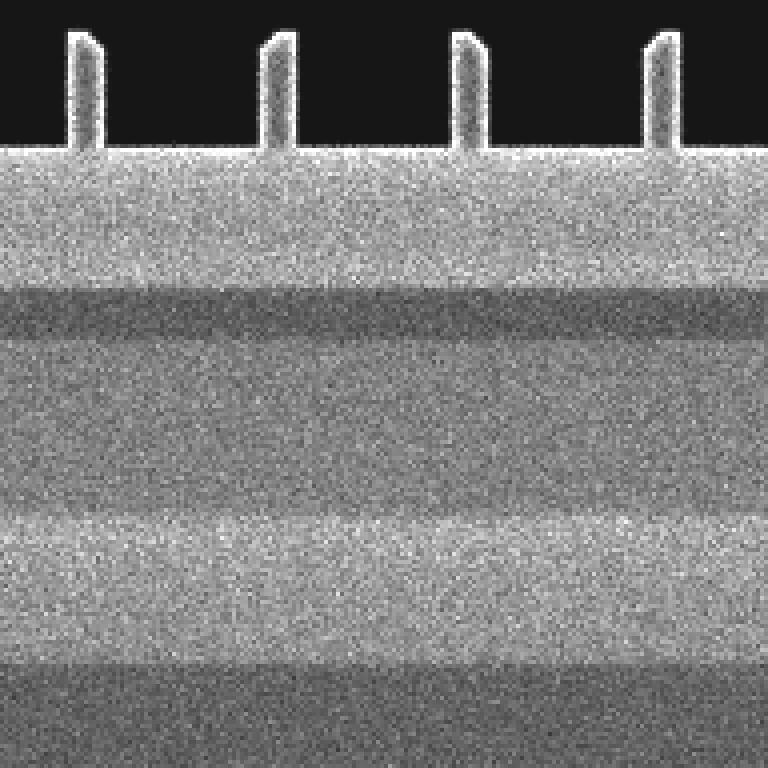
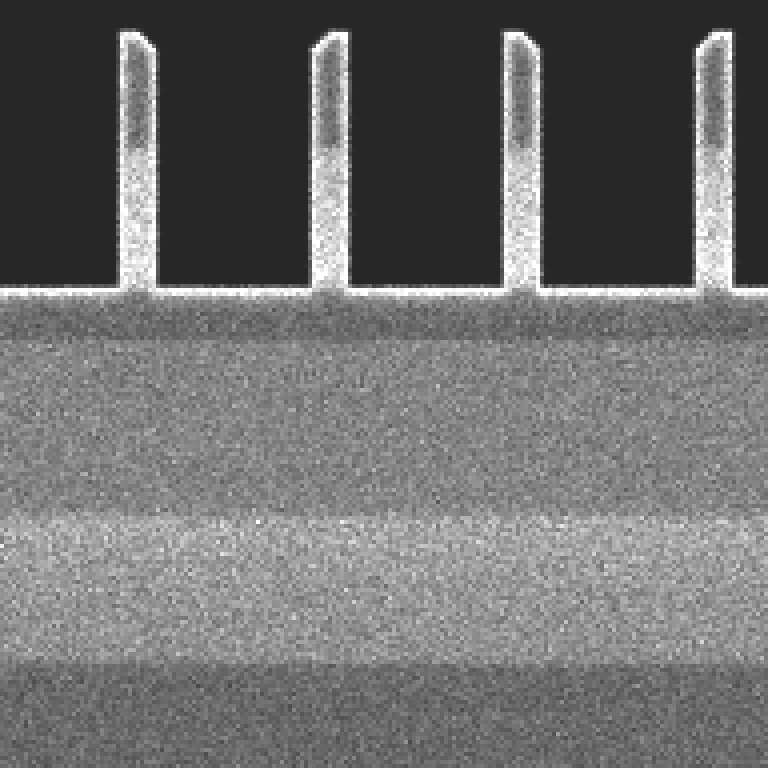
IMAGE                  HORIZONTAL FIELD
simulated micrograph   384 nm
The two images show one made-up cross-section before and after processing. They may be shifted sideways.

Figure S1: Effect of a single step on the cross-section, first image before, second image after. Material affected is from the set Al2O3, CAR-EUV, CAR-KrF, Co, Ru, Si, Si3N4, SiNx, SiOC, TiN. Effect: removed Ru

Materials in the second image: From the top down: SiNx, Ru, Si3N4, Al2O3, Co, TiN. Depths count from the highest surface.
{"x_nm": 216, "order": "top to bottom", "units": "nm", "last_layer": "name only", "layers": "empty 128, Si3N4 26, Al2O3 88, Co 74, TiN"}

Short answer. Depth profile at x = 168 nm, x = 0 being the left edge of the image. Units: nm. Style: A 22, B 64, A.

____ SiNx 58, Ru 70, Si3N4 26, Al2O3 88, Co 74, TiN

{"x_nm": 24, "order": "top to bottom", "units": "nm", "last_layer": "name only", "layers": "empty 128, Si3N4 26, Al2O3 88, Co 74, TiN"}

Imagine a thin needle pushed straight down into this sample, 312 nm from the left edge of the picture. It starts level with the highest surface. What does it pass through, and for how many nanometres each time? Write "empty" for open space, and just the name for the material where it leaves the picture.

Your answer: empty 128, Si3N4 26, Al2O3 88, Co 74, TiN